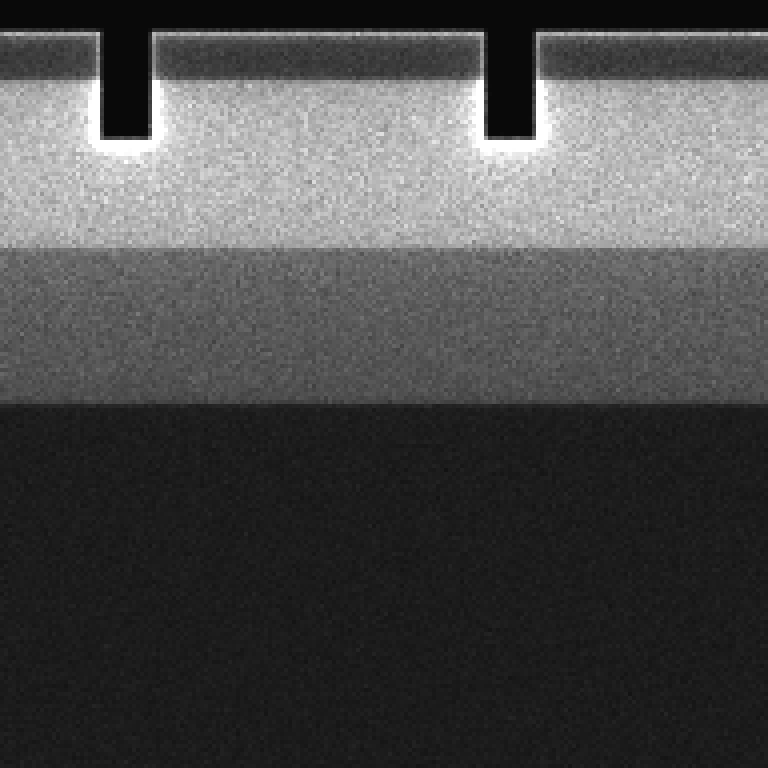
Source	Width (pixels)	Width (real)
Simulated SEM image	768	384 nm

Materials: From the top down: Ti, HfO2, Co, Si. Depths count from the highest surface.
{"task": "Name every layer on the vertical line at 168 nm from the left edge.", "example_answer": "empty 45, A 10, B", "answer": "Ti 24, HfO2 84, Co 78, Si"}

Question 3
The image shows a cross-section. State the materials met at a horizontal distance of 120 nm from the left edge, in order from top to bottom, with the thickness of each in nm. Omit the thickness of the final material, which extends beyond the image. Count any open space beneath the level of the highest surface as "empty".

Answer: Ti 24, HfO2 84, Co 78, Si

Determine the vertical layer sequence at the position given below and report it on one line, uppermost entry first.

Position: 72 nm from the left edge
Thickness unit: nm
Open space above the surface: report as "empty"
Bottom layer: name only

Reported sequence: empty 54, HfO2 54, Co 78, Si